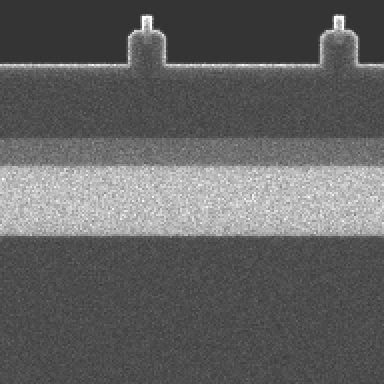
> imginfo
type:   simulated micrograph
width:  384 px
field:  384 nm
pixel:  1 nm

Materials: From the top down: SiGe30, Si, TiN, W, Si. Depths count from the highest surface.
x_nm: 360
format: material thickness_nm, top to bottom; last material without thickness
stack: empty 48, SiGe30 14, Si 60, TiN 28, W 70, Si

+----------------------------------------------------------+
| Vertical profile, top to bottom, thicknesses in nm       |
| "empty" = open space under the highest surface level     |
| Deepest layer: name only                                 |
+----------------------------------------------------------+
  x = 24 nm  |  empty 48, SiGe30 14, Si 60, TiN 28, W 70, Si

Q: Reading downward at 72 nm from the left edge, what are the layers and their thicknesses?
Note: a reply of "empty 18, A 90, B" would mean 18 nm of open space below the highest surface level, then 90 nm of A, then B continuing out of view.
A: empty 48, SiGe30 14, Si 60, TiN 28, W 70, Si